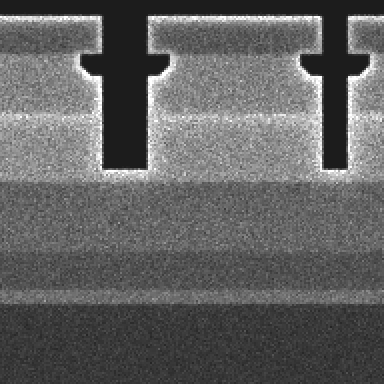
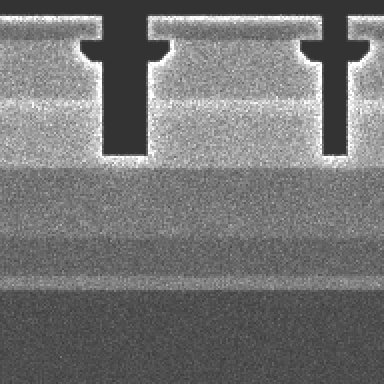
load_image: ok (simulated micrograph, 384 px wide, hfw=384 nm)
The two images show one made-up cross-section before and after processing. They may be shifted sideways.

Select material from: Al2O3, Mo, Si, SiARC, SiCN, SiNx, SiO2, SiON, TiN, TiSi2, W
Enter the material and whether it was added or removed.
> SiARC / removed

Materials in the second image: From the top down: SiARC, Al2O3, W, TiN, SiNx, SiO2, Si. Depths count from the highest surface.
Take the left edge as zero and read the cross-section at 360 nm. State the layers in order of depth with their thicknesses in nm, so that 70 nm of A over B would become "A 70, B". SiARC 24, empty 20, Al2O3 40, W 68, TiN 70, SiNx 38, SiO2 14, Si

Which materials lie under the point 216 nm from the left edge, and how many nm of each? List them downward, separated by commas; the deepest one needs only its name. SiARC 24, Al2O3 60, W 68, TiN 70, SiNx 38, SiO2 14, Si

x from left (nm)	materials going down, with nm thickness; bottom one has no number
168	SiARC 24, empty 12, Al2O3 48, W 68, TiN 70, SiNx 38, SiO2 14, Si